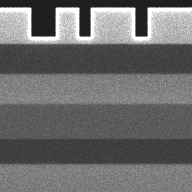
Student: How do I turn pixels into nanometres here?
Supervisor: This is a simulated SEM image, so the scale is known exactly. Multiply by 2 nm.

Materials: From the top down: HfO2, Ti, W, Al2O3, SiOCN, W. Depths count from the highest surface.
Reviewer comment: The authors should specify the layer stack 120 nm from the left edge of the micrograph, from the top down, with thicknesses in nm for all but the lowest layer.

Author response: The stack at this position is HfO2 72, Ti 60, W 60, Al2O3 70, SiOCN 50, W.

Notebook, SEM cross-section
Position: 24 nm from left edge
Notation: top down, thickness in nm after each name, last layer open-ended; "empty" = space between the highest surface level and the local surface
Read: HfO2 72, Ti 60, W 60, Al2O3 70, SiOCN 50, W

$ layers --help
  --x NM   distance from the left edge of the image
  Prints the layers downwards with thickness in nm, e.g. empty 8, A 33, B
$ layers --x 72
empty 58, HfO2 14, Ti 60, W 60, Al2O3 70, SiOCN 50, W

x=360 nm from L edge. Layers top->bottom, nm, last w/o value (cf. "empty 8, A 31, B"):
HfO2 72, Ti 60, W 60, Al2O3 70, SiOCN 50, W